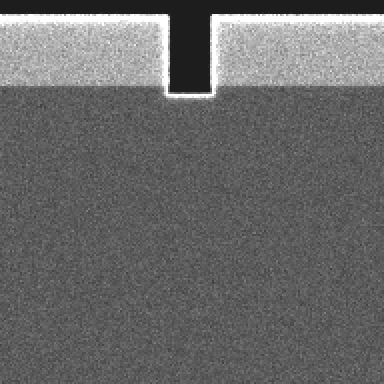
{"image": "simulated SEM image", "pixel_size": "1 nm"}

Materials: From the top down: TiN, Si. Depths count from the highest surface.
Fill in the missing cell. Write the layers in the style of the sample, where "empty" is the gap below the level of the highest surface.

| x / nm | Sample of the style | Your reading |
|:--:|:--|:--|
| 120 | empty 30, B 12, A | TiN 70, Si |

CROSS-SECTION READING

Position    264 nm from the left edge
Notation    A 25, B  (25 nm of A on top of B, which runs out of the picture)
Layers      TiN 70, Si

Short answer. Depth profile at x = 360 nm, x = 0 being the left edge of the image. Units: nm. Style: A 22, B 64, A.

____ TiN 70, Si